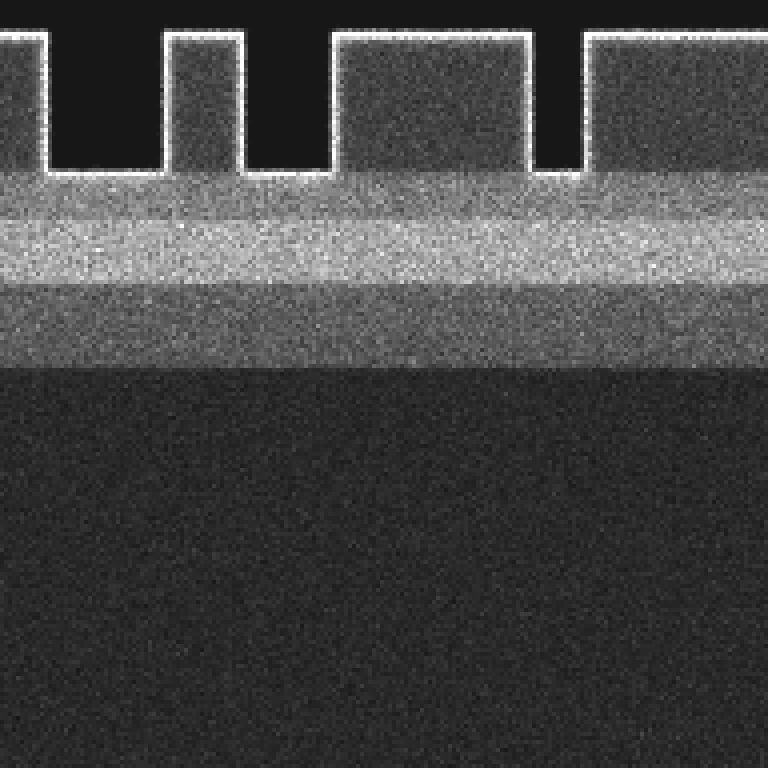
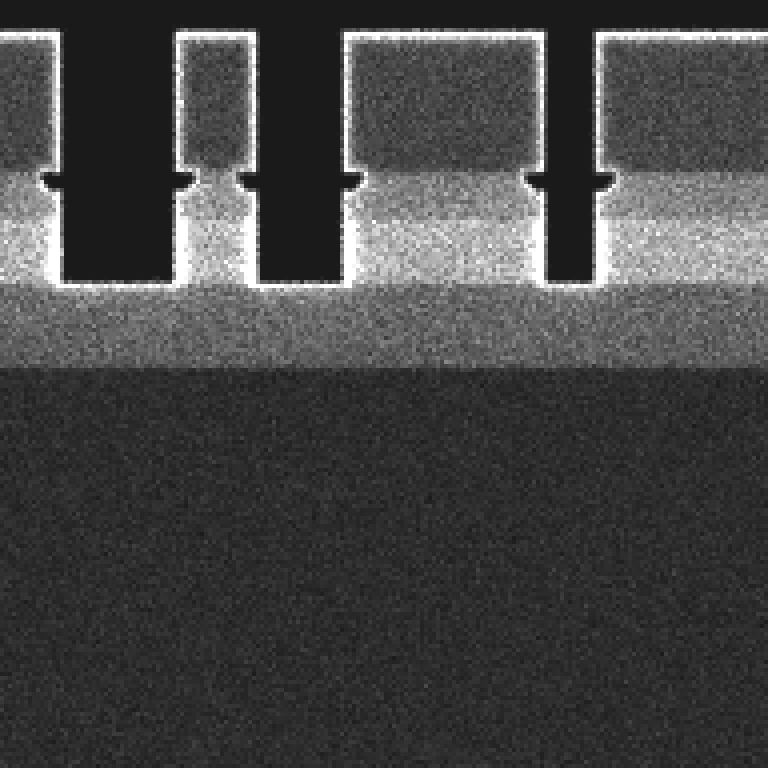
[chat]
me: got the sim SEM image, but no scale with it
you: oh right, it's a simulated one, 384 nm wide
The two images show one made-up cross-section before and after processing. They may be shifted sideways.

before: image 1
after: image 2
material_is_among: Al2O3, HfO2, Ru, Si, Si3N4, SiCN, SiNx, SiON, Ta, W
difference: HfO2 and W, removed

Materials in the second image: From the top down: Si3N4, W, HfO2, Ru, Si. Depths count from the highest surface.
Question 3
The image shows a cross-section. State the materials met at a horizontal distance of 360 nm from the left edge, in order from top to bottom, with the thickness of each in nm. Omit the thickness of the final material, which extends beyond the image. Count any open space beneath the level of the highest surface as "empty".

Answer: Si3N4 70, W 24, HfO2 32, Ru 42, Si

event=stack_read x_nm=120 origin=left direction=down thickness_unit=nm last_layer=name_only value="Si3N4 70, empty 8, W 16, HfO2 32, Ru 42, Si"